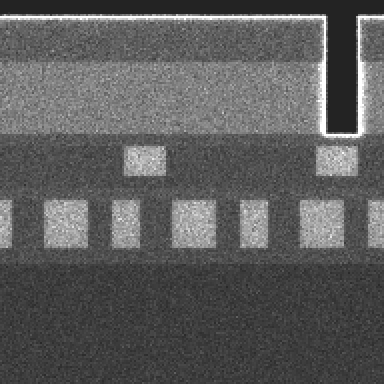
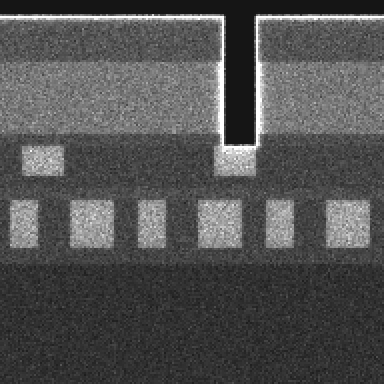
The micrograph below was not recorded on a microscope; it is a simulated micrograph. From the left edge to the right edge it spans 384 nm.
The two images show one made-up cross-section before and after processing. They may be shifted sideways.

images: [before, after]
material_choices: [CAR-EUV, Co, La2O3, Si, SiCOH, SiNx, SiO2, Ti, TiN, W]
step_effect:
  removed: SiNx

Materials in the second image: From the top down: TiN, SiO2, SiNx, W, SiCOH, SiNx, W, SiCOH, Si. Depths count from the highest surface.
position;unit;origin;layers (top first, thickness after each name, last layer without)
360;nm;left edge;TiN 46, SiO2 72, SiNx 12, SiCOH 42, SiNx 12, W 48, SiCOH 16, Si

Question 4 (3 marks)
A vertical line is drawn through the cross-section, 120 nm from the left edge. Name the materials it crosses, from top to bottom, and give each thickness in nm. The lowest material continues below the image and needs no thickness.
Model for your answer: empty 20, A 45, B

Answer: TiN 46, SiO2 72, SiNx 12, SiCOH 42, SiNx 12, SiCOH 64, Si